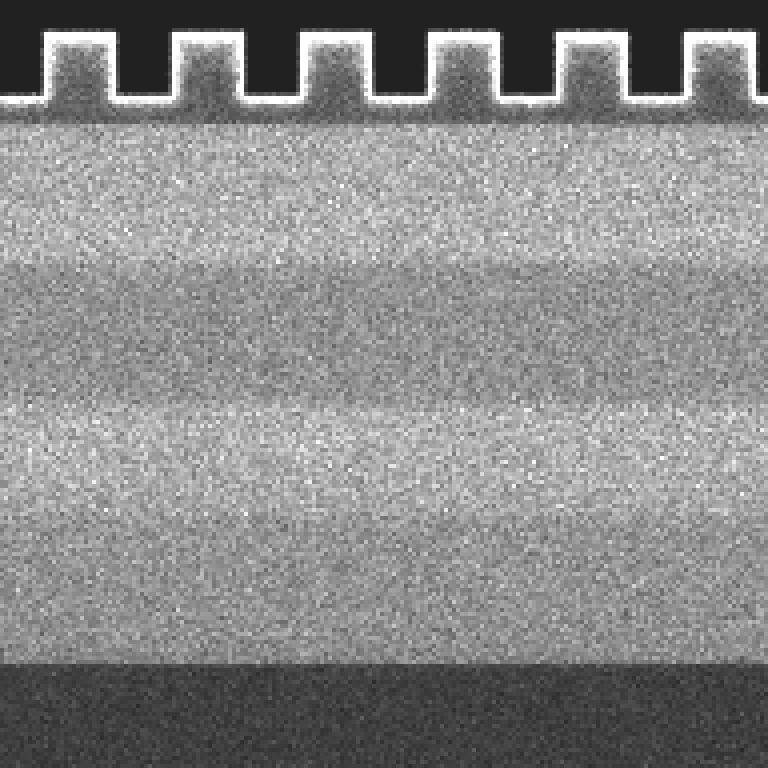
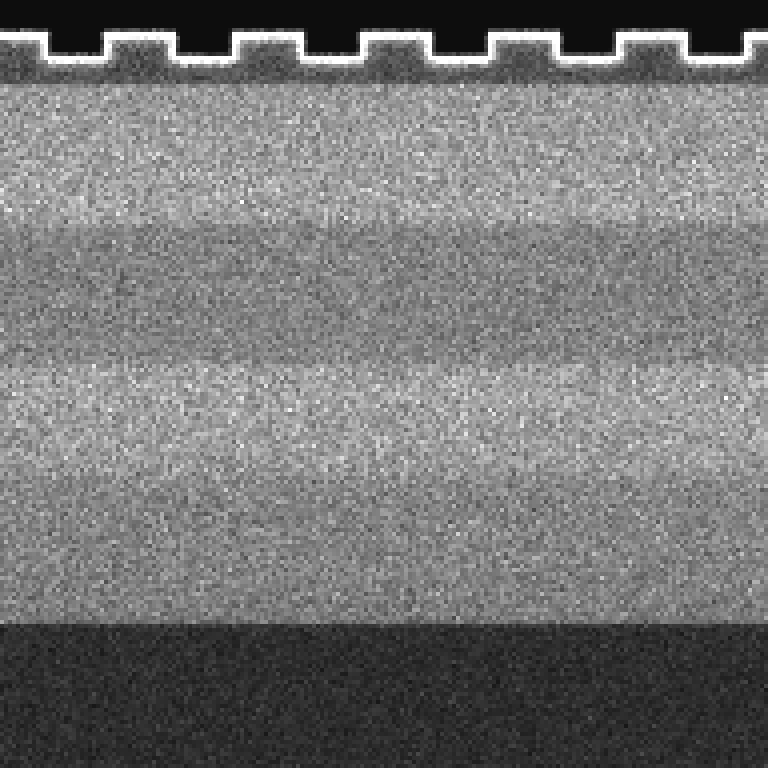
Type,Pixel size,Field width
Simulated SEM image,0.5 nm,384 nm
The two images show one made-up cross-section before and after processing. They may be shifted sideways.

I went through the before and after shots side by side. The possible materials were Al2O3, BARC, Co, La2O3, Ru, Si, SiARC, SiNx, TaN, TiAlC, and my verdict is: removed, SiARC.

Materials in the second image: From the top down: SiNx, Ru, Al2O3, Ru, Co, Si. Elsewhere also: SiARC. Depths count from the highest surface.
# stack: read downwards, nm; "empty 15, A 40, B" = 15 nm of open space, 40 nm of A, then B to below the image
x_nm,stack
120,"SiNx 26, Ru 70, Al2O3 70, Ru 56, Co 74, Si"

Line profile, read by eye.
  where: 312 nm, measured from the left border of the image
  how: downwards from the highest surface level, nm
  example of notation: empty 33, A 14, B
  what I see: SiNx 26, Ru 70, Al2O3 70, Ru 56, Co 74, Si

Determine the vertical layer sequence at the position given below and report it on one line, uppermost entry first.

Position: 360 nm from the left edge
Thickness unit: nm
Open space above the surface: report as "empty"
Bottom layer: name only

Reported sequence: empty 12, SiNx 14, Ru 70, Al2O3 70, Ru 56, Co 74, Si